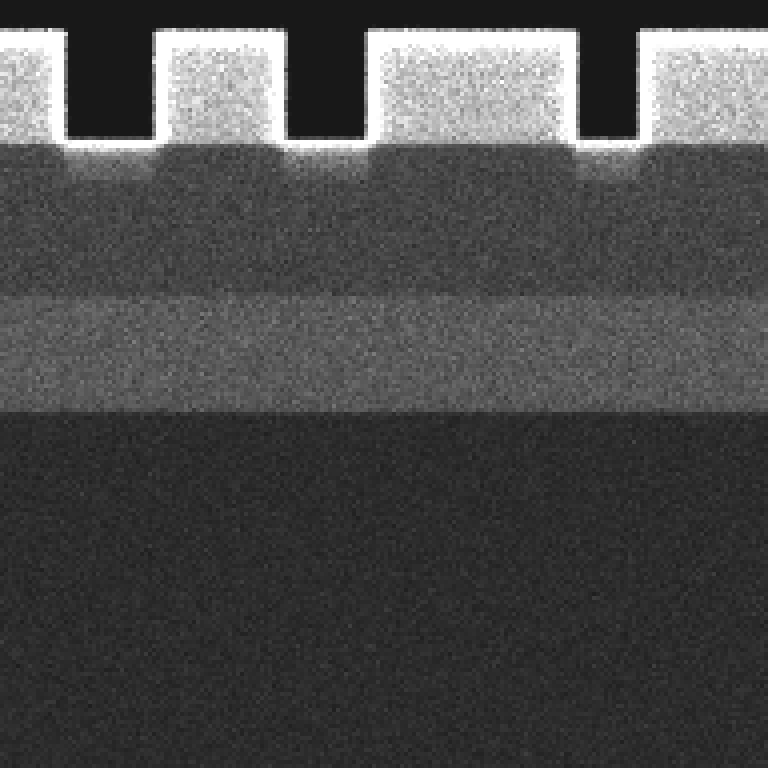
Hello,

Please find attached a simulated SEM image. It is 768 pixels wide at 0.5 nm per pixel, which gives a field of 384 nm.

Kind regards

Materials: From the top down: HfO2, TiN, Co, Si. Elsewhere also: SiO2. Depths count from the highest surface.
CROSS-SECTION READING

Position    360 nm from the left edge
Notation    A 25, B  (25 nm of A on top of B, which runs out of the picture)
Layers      HfO2 56, TiN 76, Co 58, Si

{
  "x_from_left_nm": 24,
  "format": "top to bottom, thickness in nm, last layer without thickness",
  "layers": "HfO2 56, TiN 76, Co 58, Si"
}